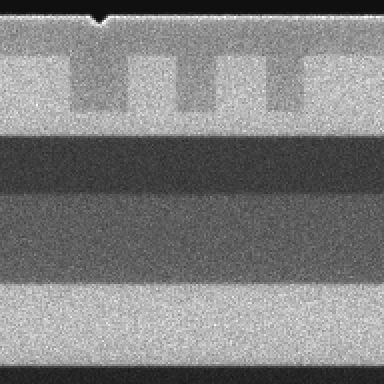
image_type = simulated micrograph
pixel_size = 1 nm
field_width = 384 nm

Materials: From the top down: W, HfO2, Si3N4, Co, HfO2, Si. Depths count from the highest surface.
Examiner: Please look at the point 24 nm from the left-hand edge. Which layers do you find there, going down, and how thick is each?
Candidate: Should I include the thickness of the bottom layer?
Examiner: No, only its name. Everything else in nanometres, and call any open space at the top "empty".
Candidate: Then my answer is W 40, HfO2 80, Si3N4 58, Co 90, HfO2 82, Si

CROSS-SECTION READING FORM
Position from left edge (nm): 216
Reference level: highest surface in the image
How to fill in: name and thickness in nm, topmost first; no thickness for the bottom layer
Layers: W 40, HfO2 80, Si3N4 58, Co 90, HfO2 82, Si